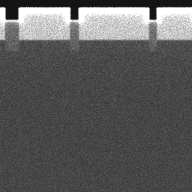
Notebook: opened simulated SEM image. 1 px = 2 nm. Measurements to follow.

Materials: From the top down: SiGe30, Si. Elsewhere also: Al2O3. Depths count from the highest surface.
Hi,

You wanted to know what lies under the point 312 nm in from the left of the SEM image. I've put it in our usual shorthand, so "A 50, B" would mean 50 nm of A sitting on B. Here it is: empty 24, SiGe30 62, Si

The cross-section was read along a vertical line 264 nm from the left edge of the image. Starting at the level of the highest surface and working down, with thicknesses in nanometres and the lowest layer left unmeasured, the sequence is Al2O3 64, Si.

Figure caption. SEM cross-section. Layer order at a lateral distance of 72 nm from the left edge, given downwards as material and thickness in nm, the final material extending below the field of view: Al2O3 64, Si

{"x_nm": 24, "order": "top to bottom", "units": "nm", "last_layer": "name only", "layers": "empty 24, SiGe30 62, Si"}